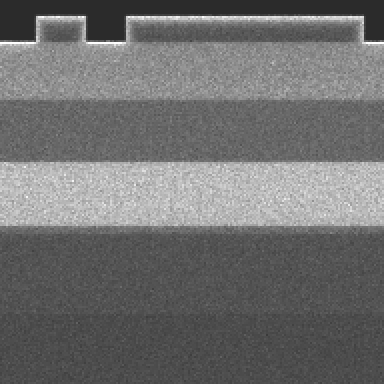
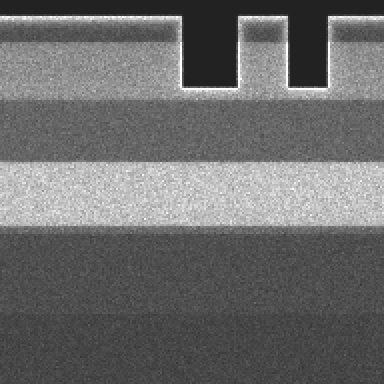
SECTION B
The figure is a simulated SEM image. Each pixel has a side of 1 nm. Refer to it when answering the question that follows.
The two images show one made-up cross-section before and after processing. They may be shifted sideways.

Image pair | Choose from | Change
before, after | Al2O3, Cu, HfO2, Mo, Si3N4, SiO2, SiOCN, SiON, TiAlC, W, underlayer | W (removed)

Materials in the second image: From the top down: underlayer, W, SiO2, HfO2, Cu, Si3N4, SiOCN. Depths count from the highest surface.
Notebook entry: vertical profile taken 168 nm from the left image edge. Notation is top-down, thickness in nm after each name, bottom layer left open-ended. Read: underlayer 26, W 58, SiO2 62, HfO2 64, Cu 8, Si3N4 80, SiOCN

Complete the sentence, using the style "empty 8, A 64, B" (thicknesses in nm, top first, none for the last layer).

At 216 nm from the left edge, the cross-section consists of empty 72, W 12, SiO2 62, HfO2 64, Cu 8, Si3N4 80, SiOCN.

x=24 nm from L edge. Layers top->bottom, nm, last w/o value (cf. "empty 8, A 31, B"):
underlayer 26, W 58, SiO2 62, HfO2 64, Cu 8, Si3N4 80, SiOCN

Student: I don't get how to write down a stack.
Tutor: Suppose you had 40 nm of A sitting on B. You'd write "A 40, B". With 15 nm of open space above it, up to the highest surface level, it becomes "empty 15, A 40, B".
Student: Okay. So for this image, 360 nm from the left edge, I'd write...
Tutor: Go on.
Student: underlayer 26, W 58, SiO2 62, HfO2 64, Cu 8, Si3N4 80, SiOCN